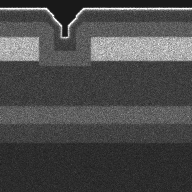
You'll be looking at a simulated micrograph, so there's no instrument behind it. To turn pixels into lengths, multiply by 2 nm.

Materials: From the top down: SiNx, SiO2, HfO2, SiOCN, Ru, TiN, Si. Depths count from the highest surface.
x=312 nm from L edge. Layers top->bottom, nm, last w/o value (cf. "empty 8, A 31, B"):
SiNx 28, SiO2 30, HfO2 48, SiOCN 90, Ru 36, TiN 38, Si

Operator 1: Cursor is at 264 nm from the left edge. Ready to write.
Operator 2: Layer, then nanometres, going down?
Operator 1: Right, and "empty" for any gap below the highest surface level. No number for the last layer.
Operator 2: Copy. SiNx 28, SiO2 30, HfO2 48, SiOCN 90, Ru 36, TiN 38, Si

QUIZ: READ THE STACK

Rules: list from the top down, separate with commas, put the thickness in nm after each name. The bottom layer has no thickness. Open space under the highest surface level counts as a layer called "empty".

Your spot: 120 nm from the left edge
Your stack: empty 32, SiNx 54, SiO2 30, SiOCN 80, Ru 36, TiN 38, Si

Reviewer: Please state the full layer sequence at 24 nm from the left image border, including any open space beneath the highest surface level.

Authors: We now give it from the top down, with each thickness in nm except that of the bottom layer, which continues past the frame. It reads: SiNx 28, SiO2 30, HfO2 48, SiOCN 90, Ru 36, TiN 38, Si